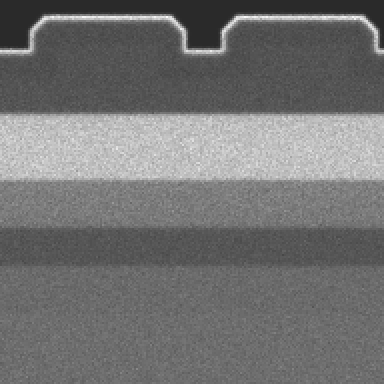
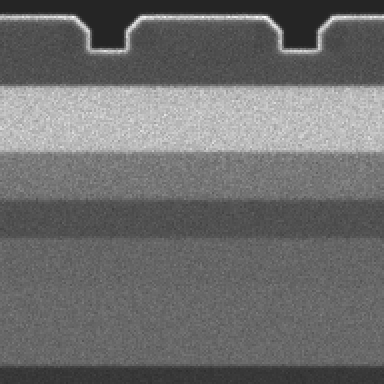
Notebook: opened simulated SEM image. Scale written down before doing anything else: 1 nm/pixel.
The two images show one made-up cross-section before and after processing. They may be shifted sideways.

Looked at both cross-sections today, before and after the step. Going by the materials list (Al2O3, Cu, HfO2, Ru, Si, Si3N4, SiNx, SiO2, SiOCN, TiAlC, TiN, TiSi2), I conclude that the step removed SiNx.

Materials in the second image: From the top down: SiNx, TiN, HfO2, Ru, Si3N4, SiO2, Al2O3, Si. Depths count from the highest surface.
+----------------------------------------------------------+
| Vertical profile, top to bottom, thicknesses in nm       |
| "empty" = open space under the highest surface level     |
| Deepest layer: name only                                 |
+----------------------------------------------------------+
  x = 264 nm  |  SiNx 34, TiN 36, HfO2 66, Ru 48, Si3N4 38, SiO2 48, Al2O3 80, Si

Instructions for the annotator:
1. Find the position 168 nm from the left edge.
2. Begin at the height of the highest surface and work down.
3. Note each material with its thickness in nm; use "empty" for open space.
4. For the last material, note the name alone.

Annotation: TiN 70, HfO2 66, Ru 48, Si3N4 38, SiO2 48, Al2O3 80, Si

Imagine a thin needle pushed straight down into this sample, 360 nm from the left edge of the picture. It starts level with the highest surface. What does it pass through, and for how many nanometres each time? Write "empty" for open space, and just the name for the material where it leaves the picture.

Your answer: TiN 70, HfO2 66, Ru 48, Si3N4 38, SiO2 48, Al2O3 80, Si